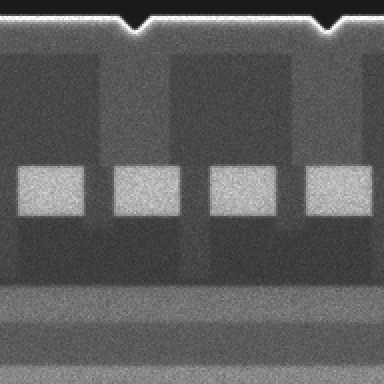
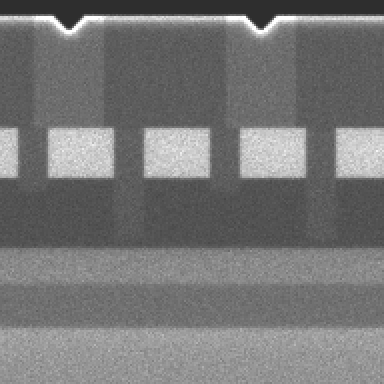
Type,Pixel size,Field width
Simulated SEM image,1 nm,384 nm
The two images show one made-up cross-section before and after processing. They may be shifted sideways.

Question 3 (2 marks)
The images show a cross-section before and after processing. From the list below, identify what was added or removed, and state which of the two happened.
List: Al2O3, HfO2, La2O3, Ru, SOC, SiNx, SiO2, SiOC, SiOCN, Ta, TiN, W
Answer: SiO2 was removed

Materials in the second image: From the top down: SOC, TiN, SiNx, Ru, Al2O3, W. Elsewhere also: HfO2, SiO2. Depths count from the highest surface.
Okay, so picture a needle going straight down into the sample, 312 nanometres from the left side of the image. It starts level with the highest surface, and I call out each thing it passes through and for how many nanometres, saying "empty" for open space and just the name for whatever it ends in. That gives SOC 112, TiN 112, SiNx 8, Ru 36, Al2O3 44, W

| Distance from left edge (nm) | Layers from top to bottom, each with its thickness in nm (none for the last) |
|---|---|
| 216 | SOC 112, TiN 64, SiNx 56, Ru 36, Al2O3 44, W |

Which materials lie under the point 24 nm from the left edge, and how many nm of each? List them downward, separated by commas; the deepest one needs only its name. SOC 112, TiN 64, SiNx 56, Ru 36, Al2O3 44, W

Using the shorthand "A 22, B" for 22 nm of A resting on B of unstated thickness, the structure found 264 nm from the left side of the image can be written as empty 12, SiO2 100, HfO2 50, SiNx 70, Ru 36, Al2O3 44, W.